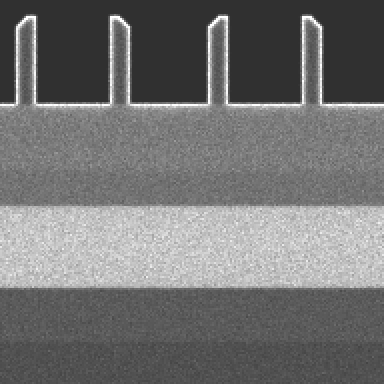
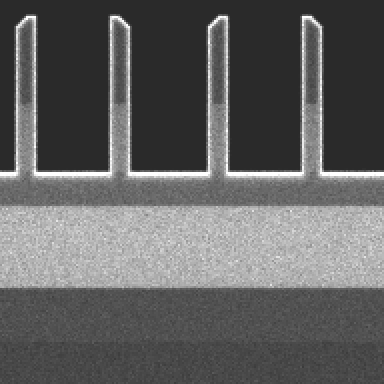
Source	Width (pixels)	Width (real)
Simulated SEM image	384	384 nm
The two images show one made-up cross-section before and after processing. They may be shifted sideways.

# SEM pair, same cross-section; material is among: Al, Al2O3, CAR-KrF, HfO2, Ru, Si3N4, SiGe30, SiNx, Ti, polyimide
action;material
removed;Ru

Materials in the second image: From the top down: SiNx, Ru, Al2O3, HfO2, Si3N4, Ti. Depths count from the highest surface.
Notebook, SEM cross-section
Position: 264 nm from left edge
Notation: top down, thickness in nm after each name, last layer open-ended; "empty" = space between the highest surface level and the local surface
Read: empty 156, Al2O3 34, HfO2 82, Si3N4 54, Ti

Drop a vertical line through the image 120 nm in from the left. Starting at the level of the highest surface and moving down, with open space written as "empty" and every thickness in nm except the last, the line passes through empty 2, SiNx 86, Ru 68, Al2O3 34, HfO2 82, Si3N4 54, Ti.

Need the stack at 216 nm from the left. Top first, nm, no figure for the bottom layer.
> empty 2, SiNx 86, Ru 68, Al2O3 34, HfO2 82, Si3N4 54, Ti